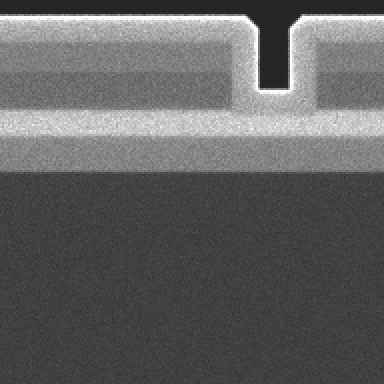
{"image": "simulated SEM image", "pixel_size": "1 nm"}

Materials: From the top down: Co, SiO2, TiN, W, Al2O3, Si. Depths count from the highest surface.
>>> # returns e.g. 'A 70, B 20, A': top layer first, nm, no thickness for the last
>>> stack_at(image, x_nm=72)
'Co 26, SiO2 30, TiN 38, W 26, Al2O3 36, Si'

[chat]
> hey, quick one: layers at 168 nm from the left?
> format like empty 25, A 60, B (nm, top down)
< Co 26, SiO2 30, TiN 38, W 26, Al2O3 36, Si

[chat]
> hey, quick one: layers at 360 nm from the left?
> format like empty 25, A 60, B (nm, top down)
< Co 26, SiO2 30, TiN 38, W 26, Al2O3 36, Si